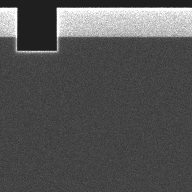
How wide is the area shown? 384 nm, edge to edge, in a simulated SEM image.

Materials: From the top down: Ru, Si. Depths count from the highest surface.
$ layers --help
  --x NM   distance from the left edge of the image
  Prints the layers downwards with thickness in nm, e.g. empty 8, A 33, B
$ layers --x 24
Ru 58, Si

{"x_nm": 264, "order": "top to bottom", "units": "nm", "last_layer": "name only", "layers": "Ru 58, Si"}